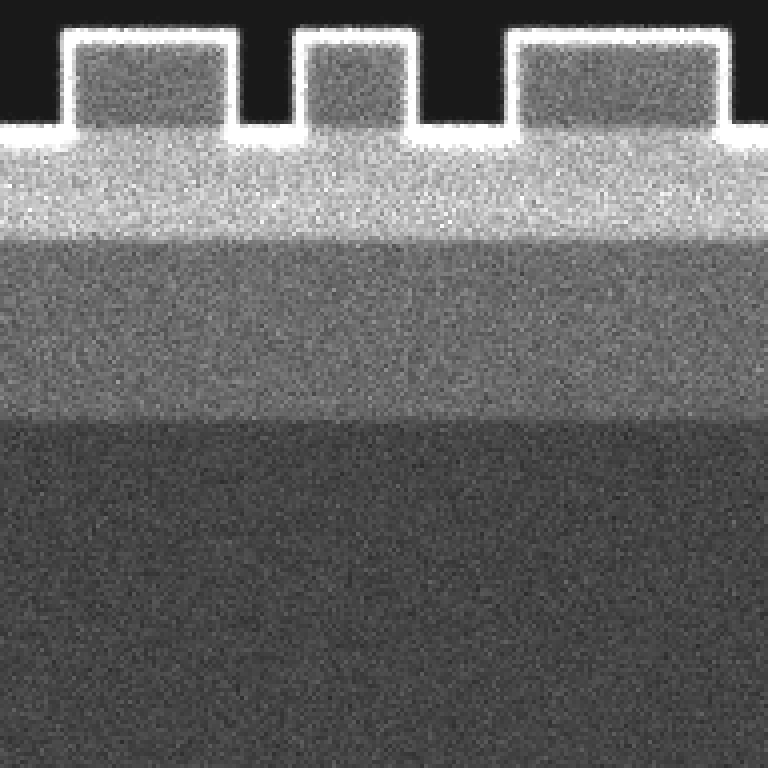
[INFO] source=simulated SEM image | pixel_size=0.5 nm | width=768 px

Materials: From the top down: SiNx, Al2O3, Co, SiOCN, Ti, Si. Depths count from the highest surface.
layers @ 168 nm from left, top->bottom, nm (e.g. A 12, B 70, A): SiNx 48, Al2O3 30, Co 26, SiOCN 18, Ti 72, Si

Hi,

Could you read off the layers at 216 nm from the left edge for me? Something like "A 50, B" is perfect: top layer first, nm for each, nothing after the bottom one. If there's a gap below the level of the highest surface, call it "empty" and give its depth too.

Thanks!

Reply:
empty 48, Al2O3 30, Co 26, SiOCN 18, Ti 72, Si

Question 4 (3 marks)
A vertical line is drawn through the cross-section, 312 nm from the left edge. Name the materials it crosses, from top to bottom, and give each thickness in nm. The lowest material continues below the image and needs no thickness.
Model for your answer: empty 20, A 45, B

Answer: SiNx 48, Al2O3 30, Co 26, SiOCN 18, Ti 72, Si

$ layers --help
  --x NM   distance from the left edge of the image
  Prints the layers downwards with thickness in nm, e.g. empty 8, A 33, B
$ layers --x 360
SiNx 48, Al2O3 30, Co 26, SiOCN 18, Ti 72, Si